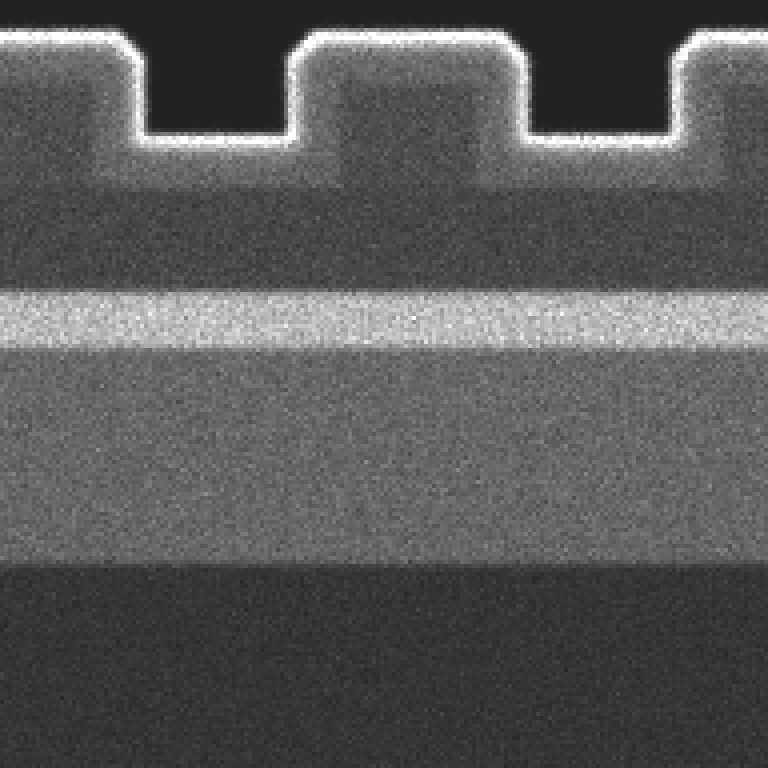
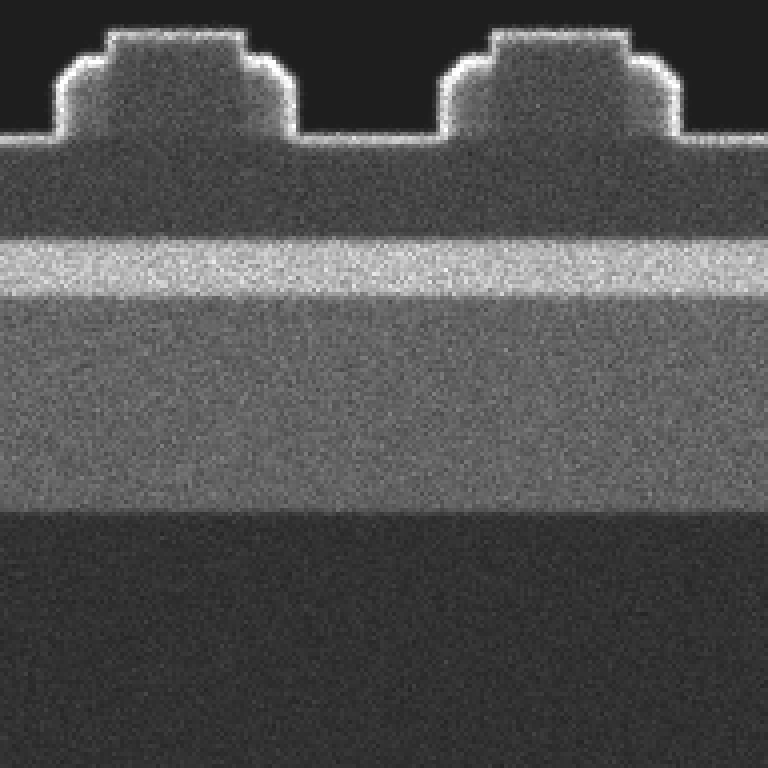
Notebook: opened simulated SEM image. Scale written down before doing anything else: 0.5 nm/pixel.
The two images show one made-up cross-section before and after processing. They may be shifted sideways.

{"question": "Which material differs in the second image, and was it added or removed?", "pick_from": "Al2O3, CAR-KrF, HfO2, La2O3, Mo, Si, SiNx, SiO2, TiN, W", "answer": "SiO2, removed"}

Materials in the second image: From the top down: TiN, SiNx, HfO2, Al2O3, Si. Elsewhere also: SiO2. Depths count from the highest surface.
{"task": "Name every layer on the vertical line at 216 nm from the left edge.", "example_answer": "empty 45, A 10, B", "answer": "empty 52, SiNx 52, HfO2 28, Al2O3 108, Si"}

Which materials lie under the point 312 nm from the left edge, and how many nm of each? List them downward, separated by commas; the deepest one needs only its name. TiN 52, SiNx 52, HfO2 28, Al2O3 108, Si